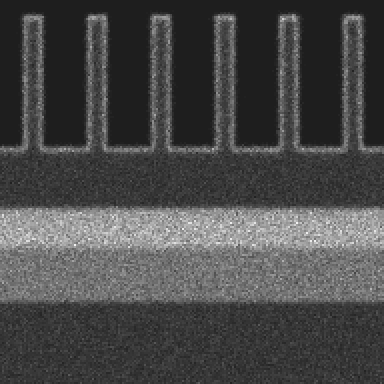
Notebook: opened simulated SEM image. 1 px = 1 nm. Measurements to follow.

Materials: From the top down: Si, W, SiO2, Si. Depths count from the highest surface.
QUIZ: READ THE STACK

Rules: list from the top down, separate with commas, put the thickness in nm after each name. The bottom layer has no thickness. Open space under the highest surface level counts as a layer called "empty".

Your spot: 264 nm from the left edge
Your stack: empty 132, Si 60, W 40, SiO2 54, Si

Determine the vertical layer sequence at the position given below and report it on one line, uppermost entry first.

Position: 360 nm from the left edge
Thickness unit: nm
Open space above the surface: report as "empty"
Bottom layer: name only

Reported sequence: Si 192, W 40, SiO2 54, Si